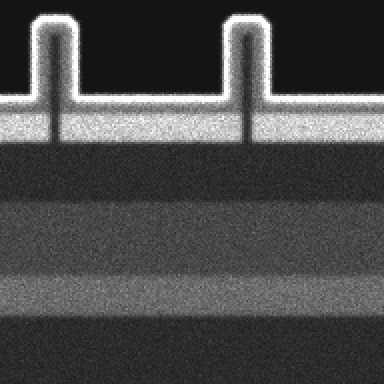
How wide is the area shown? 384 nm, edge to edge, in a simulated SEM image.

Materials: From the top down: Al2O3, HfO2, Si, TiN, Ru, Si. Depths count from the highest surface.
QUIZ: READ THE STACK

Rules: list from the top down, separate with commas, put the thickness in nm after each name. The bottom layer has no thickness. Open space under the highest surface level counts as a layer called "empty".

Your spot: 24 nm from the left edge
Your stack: empty 80, Al2O3 18, HfO2 28, Si 60, TiN 74, Ru 40, Si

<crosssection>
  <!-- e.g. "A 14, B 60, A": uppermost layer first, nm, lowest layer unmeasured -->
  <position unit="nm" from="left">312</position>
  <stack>empty 80, Al2O3 18, HfO2 28, Si 60, TiN 74, Ru 40, Si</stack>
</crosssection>